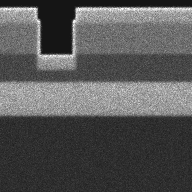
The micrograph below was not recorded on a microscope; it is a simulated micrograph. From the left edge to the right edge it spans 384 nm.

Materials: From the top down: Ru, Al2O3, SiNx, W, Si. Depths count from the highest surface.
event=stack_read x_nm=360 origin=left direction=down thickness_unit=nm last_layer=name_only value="Ru 30, Al2O3 62, SiNx 56, W 68, Si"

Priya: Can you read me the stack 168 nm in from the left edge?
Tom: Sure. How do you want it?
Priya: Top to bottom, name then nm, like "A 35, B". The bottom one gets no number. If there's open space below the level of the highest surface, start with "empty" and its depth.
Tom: Ru 30, Al2O3 62, SiNx 56, W 68, Si